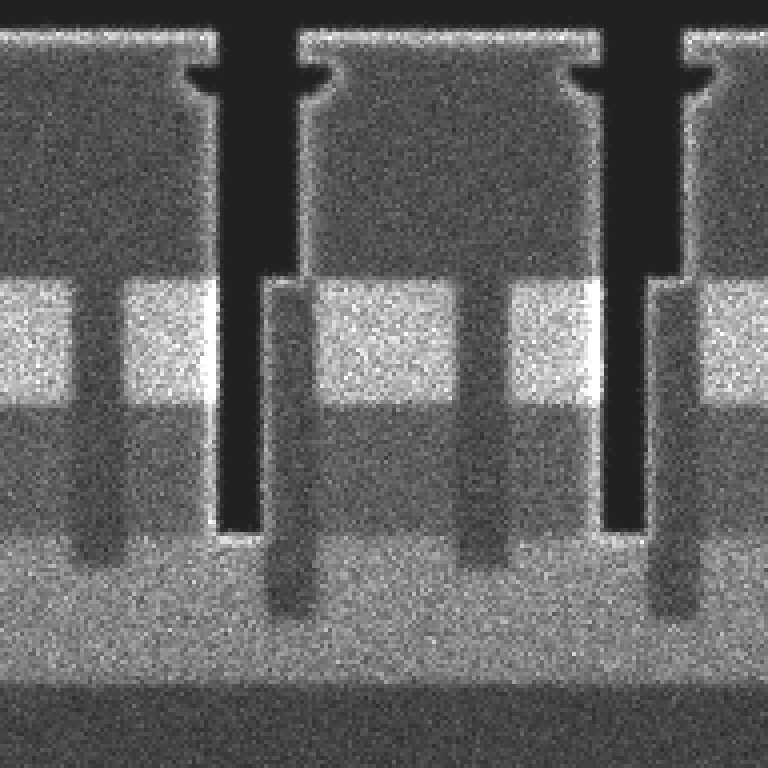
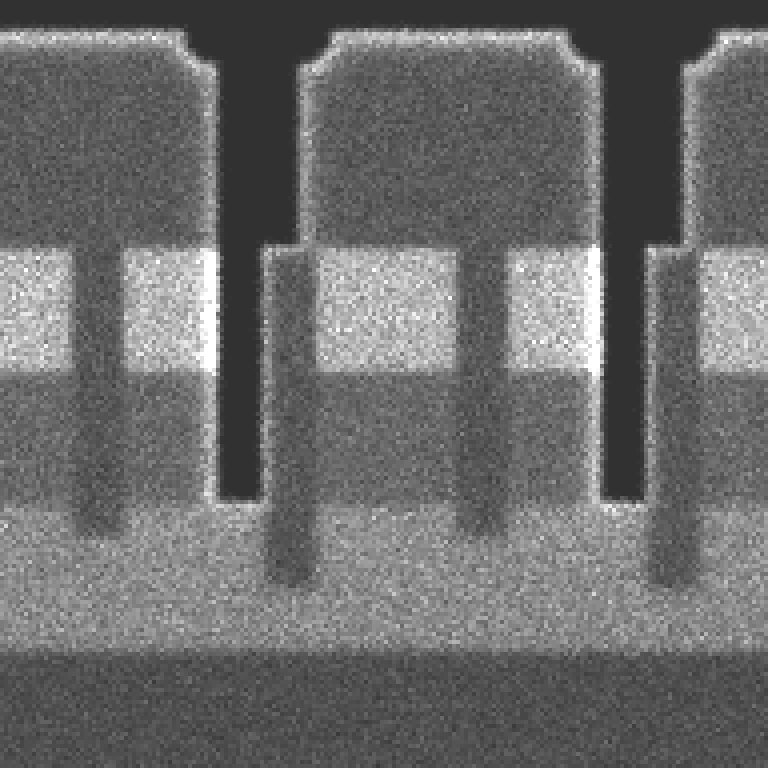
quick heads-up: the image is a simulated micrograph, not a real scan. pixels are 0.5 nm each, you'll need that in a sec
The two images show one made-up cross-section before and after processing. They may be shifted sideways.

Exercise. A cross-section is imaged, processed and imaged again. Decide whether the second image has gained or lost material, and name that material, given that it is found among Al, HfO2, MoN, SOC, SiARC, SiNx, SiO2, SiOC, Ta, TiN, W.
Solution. removed: SiARC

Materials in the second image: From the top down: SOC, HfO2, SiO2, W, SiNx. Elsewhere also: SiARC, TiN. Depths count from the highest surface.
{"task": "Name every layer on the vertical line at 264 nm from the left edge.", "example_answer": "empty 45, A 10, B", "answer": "SOC 108, HfO2 62, SiO2 66, W 74, SiNx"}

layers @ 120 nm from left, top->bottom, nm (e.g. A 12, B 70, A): empty 236, W 74, SiNx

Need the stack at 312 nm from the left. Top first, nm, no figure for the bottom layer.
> empty 236, W 74, SiNx